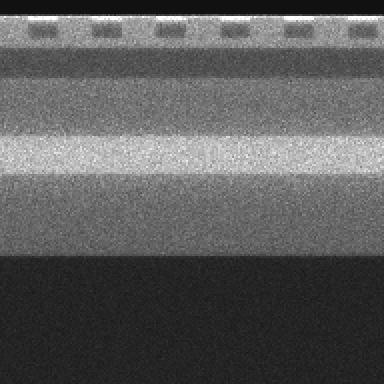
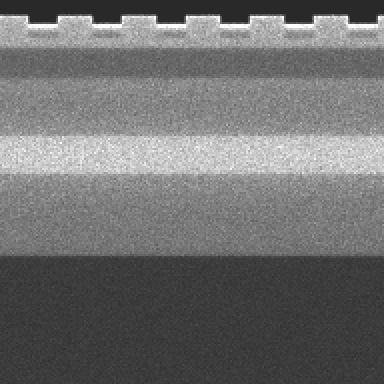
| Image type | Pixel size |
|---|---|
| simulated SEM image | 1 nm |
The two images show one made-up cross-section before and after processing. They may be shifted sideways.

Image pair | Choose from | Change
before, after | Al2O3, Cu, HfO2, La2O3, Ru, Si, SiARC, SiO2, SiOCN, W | Al2O3 (removed)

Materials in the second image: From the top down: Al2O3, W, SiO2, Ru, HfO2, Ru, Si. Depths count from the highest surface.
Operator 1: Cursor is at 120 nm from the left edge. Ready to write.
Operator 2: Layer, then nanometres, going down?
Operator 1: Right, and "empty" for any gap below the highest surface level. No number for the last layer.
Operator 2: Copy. empty 8, Al2O3 14, W 10, SiO2 30, Ru 58, HfO2 38, Ru 82, Si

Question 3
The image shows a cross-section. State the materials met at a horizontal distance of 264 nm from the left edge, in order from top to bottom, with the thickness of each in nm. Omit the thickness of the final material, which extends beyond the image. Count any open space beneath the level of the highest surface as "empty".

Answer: W 32, SiO2 30, Ru 58, HfO2 38, Ru 82, Si